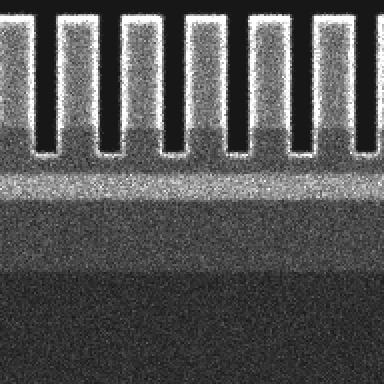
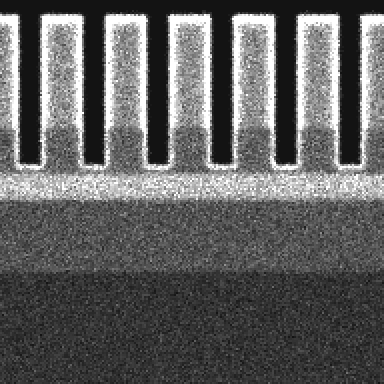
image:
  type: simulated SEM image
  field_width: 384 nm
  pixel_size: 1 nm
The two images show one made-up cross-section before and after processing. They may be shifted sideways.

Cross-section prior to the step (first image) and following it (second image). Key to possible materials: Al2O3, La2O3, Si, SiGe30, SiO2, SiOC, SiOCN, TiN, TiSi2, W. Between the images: TiN was removed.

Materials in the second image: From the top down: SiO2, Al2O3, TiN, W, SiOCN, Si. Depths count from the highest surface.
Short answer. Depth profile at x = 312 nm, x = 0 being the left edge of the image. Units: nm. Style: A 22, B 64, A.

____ SiO2 36, Al2O3 76, TiN 46, W 26, SiOCN 72, Si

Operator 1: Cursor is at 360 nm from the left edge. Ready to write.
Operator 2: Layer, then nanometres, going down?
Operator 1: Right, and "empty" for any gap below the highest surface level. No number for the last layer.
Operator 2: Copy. empty 150, TiN 8, W 26, SiOCN 72, Si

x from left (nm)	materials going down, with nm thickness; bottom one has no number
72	SiO2 36, Al2O3 76, TiN 46, W 26, SiOCN 72, Si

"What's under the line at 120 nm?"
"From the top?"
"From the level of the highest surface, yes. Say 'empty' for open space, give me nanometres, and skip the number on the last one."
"SiO2 36, Al2O3 76, TiN 46, W 26, SiOCN 72, Si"